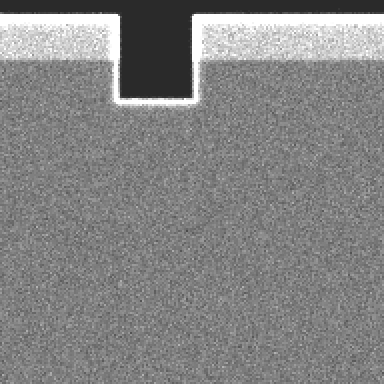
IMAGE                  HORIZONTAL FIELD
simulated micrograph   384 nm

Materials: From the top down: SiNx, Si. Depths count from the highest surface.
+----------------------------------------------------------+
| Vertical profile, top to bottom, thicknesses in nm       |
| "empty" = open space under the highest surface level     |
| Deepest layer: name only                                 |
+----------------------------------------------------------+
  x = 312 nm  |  SiNx 44, Si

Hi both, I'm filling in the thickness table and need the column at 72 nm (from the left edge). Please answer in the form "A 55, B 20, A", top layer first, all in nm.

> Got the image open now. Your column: SiNx 44, Si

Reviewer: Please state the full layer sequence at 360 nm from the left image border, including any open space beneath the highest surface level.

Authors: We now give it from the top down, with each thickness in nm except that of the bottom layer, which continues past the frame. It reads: SiNx 44, Si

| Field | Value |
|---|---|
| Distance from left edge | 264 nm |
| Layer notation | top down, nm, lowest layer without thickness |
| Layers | SiNx 44, Si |